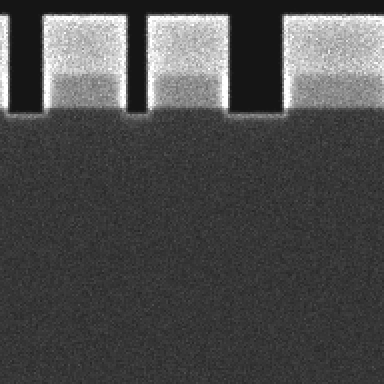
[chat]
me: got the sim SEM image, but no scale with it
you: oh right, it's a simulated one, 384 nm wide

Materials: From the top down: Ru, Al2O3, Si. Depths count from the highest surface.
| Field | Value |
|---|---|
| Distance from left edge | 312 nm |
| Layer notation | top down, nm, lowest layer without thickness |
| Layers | Ru 58, Al2O3 34, Si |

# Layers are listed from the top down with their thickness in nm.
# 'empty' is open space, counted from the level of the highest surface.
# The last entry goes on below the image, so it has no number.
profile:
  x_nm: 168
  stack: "Ru 58, Al2O3 34, Si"